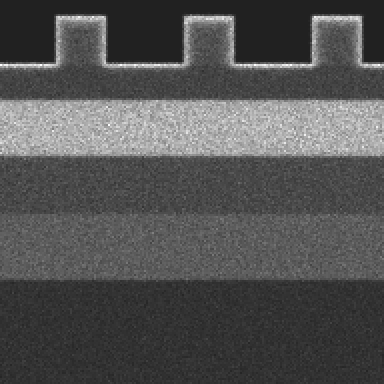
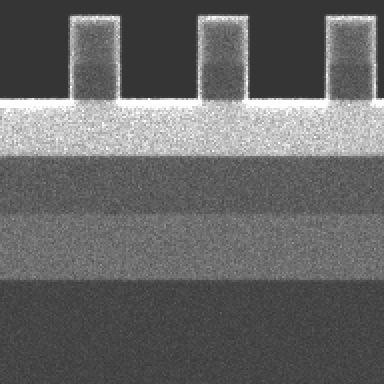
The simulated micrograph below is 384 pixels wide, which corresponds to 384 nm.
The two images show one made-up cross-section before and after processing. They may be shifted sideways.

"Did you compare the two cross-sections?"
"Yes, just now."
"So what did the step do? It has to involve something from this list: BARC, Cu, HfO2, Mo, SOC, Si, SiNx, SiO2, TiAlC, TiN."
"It removed SiNx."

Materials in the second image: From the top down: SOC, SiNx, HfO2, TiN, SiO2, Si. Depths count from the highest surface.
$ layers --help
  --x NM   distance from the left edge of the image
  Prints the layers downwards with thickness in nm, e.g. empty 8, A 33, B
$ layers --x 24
empty 84, HfO2 56, TiN 58, SiO2 66, Si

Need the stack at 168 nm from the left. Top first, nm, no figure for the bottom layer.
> empty 84, HfO2 56, TiN 58, SiO2 66, Si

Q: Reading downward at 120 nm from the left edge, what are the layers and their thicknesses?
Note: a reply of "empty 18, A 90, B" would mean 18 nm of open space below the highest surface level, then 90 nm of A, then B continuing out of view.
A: empty 84, HfO2 56, TiN 58, SiO2 66, Si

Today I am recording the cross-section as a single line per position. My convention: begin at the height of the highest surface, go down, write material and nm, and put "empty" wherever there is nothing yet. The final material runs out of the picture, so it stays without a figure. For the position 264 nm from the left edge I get empty 84, HfO2 56, TiN 58, SiO2 66, Si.